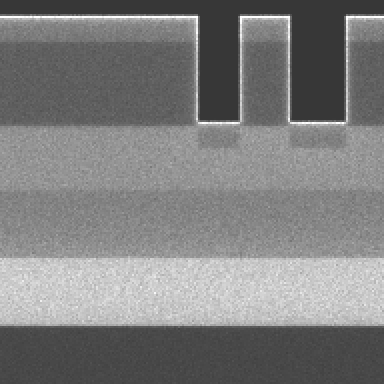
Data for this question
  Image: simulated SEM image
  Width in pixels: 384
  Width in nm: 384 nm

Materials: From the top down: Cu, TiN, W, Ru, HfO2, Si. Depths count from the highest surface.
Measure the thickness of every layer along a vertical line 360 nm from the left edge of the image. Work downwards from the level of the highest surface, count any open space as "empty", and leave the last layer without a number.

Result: Cu 26, TiN 84, W 64, Ru 68, HfO2 68, Si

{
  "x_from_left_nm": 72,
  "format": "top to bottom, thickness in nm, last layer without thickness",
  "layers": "Cu 26, TiN 84, W 64, Ru 68, HfO2 68, Si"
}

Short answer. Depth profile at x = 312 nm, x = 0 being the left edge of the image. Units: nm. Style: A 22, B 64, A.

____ empty 106, Cu 26, W 42, Ru 68, HfO2 68, Si